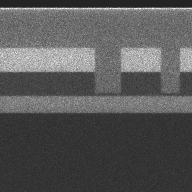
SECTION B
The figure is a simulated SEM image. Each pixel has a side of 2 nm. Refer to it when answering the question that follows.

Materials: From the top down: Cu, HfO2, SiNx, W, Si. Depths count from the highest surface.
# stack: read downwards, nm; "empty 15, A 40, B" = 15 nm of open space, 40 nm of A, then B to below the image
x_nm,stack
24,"Cu 80, HfO2 48, SiNx 48, W 34, Si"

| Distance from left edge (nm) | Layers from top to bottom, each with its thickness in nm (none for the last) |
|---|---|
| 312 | Cu 80, HfO2 48, SiNx 48, W 34, Si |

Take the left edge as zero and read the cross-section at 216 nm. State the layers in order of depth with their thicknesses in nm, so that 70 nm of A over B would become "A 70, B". Cu 170, SiNx 6, W 34, Si